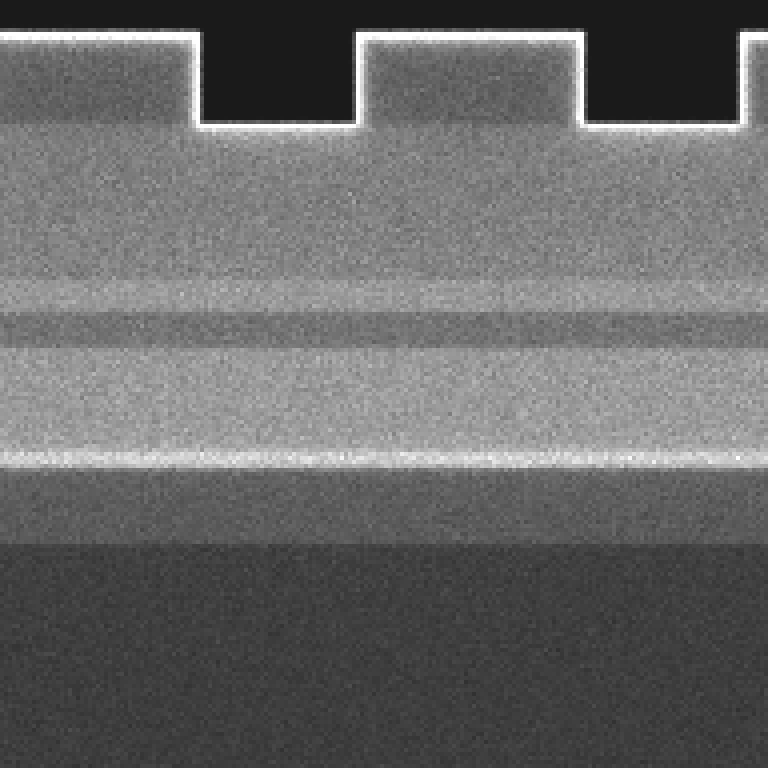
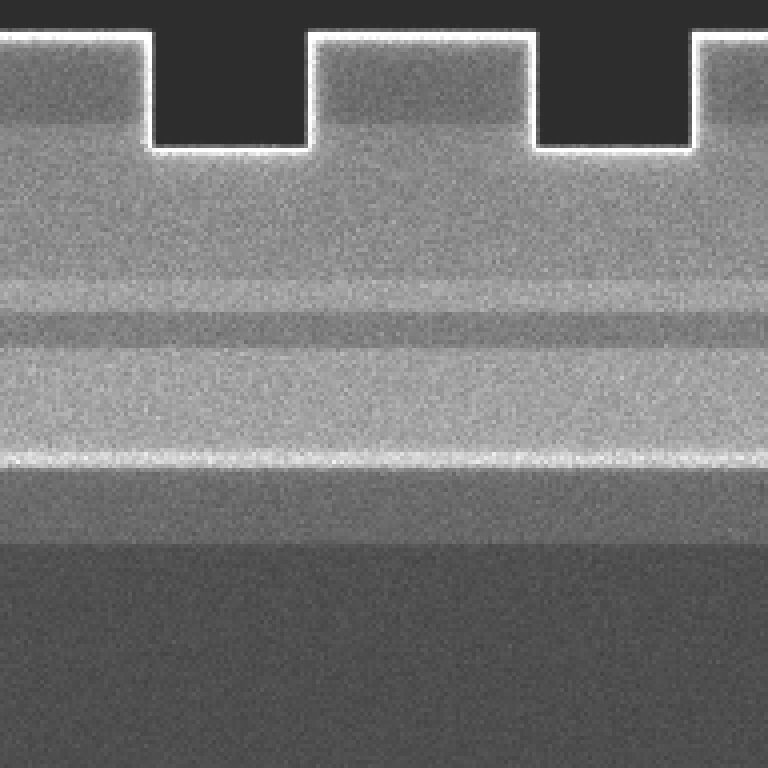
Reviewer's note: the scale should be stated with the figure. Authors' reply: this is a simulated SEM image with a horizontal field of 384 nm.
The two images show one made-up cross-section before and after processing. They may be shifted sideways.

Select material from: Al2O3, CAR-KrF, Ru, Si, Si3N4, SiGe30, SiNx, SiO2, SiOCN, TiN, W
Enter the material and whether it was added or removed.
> TiN / removed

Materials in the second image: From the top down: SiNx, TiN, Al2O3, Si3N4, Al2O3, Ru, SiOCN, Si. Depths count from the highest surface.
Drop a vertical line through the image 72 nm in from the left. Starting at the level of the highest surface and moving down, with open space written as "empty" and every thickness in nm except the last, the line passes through SiNx 46, TiN 78, Al2O3 16, Si3N4 18, Al2O3 52, Ru 8, SiOCN 38, Si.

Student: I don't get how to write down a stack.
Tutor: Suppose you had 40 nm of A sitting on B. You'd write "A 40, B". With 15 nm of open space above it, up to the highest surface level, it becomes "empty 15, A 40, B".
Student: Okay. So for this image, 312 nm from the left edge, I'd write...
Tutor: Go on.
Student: empty 58, TiN 66, Al2O3 16, Si3N4 18, Al2O3 52, Ru 8, SiOCN 38, Si